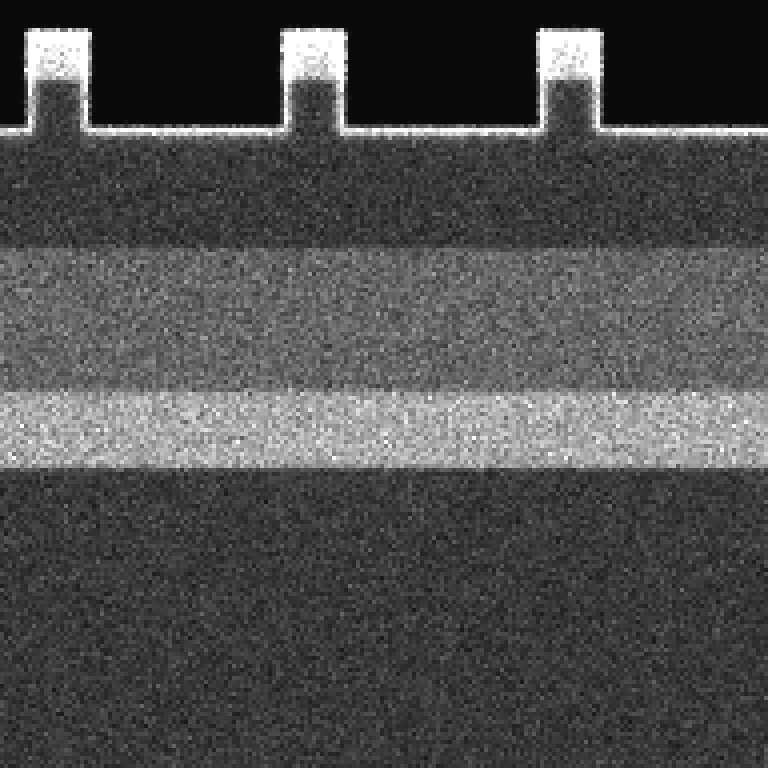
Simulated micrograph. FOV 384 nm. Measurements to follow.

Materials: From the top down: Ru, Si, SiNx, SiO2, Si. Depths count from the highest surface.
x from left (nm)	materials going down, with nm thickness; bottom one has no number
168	Ru 24, Si 84, SiNx 72, SiO2 38, Si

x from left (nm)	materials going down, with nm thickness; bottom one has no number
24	Ru 24, Si 84, SiNx 72, SiO2 38, Si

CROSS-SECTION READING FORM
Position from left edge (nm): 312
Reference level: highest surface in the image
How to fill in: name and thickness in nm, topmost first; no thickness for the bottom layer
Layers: empty 48, Si 60, SiNx 72, SiO2 38, Si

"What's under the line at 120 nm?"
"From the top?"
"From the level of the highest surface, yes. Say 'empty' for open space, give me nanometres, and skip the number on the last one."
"empty 48, Si 60, SiNx 72, SiO2 38, Si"